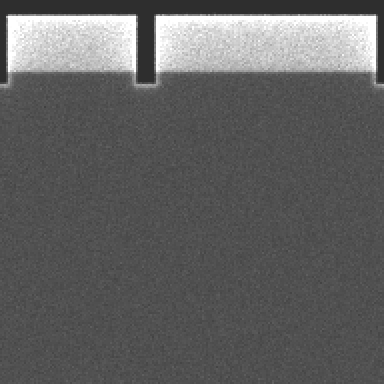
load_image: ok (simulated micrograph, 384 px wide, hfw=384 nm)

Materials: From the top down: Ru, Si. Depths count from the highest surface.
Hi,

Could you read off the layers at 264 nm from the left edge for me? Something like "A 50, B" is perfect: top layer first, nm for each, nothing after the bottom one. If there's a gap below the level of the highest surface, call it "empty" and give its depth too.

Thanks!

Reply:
Ru 56, Si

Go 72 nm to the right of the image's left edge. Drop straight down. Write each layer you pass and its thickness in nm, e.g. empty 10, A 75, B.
Ru 56, Si